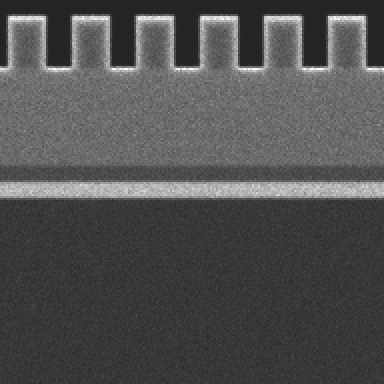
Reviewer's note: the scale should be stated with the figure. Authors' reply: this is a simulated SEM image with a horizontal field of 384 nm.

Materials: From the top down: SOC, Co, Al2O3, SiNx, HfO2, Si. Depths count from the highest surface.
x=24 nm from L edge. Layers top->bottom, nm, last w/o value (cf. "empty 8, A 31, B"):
SOC 52, Co 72, Al2O3 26, SiNx 16, HfO2 16, Si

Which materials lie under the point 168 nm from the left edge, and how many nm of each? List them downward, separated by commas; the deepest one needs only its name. SOC 52, Co 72, Al2O3 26, SiNx 16, HfO2 16, Si